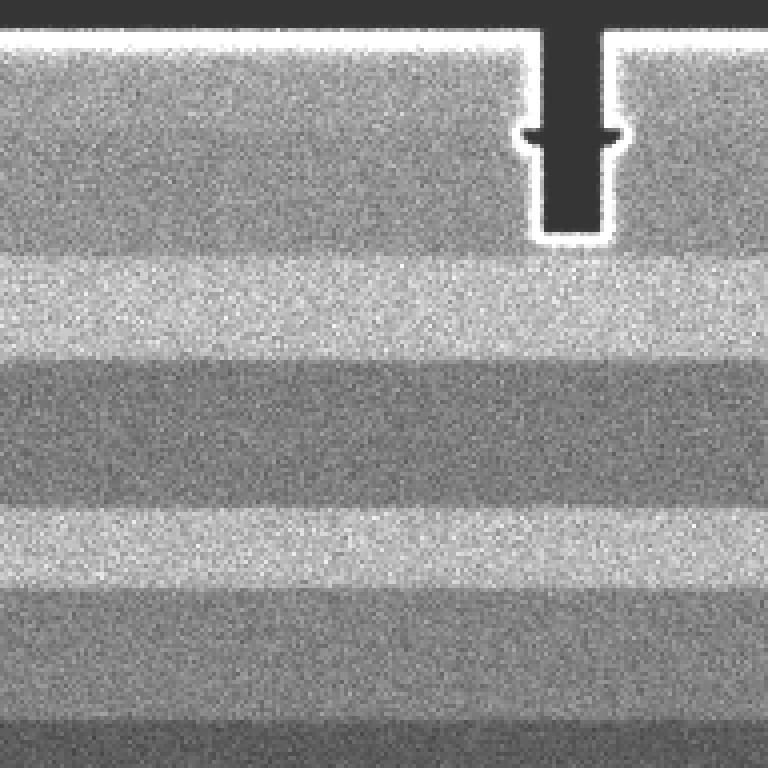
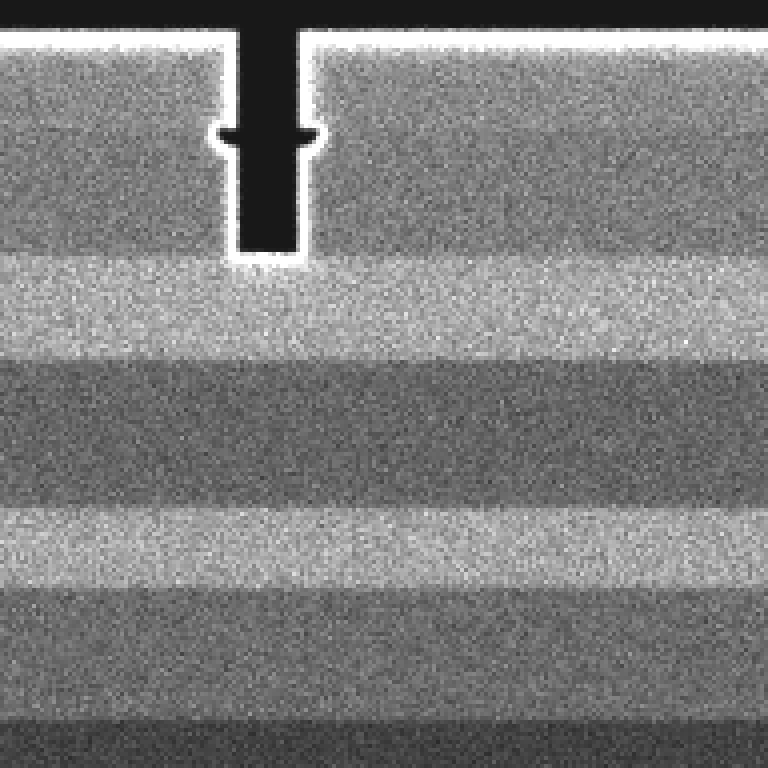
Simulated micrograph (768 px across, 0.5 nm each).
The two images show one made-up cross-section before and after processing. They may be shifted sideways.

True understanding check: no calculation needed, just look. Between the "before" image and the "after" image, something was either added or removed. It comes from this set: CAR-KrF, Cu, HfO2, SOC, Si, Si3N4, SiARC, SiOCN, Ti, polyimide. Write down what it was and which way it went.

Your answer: Si3N4 (removed)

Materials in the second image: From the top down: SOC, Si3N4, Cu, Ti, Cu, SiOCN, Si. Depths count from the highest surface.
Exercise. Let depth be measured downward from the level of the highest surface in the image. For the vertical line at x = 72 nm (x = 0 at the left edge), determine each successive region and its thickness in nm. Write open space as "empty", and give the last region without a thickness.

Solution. SOC 48, Si3N4 64, Cu 52, Ti 74, Cu 40, SiOCN 66, Si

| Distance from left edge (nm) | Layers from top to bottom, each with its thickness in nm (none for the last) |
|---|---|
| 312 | SOC 48, Si3N4 64, Cu 52, Ti 74, Cu 40, SiOCN 66, Si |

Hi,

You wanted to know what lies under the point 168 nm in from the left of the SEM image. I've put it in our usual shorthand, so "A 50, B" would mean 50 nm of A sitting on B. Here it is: SOC 48, Si3N4 64, Cu 52, Ti 74, Cu 40, SiOCN 66, Si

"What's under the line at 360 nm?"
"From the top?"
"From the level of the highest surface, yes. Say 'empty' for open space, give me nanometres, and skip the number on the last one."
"SOC 48, Si3N4 64, Cu 52, Ti 74, Cu 40, SiOCN 66, Si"